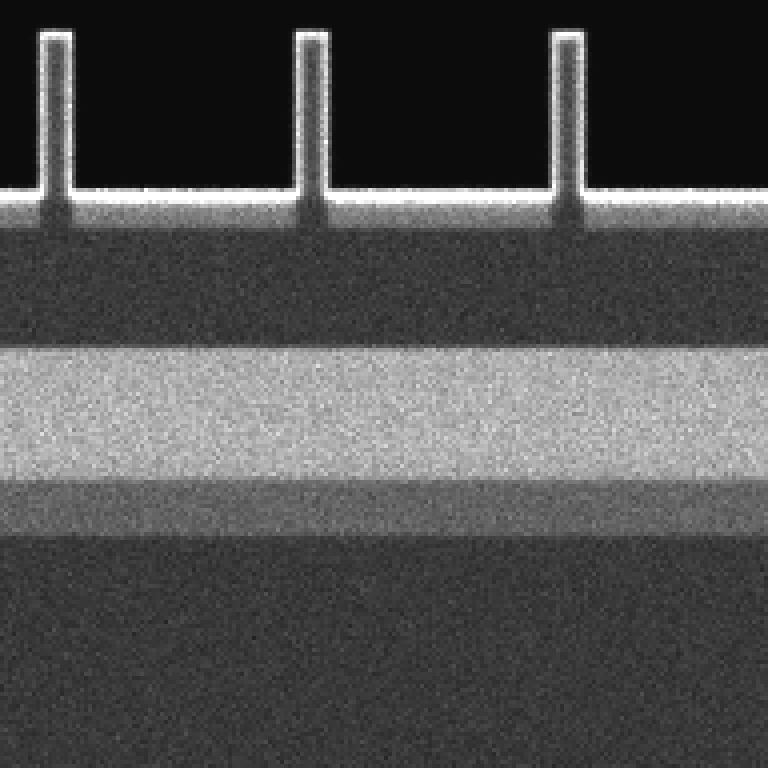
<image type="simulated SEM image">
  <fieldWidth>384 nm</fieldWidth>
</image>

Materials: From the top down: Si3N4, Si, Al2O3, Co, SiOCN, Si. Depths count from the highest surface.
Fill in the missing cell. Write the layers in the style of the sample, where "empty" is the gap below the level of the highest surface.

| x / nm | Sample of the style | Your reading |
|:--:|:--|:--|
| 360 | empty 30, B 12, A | empty 80, Si3N4 18, Si 60, Al2O3 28, Co 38, SiOCN 28, Si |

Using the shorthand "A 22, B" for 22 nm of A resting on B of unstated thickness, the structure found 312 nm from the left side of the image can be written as empty 80, Si3N4 18, Si 60, Al2O3 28, Co 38, SiOCN 28, Si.